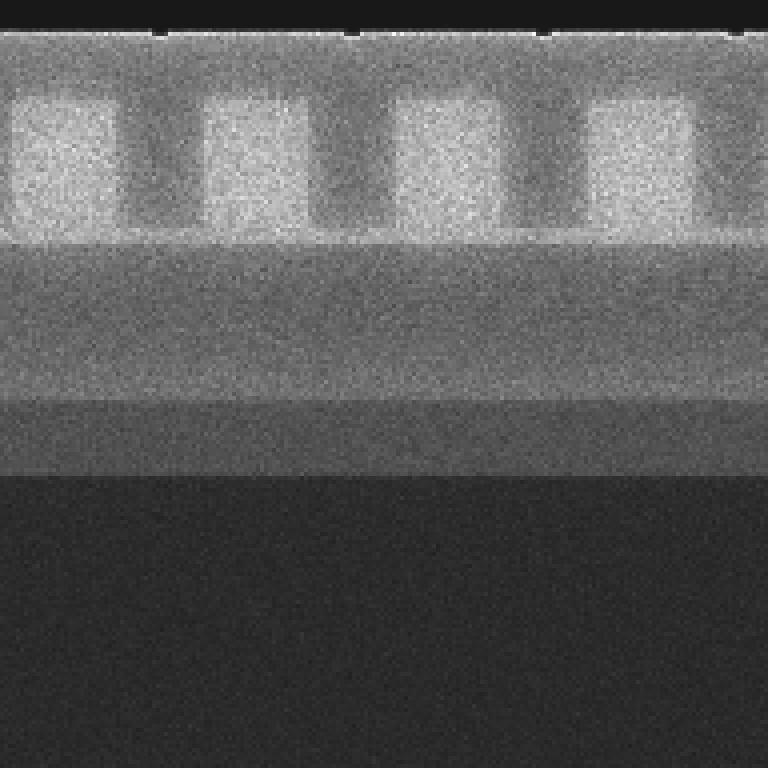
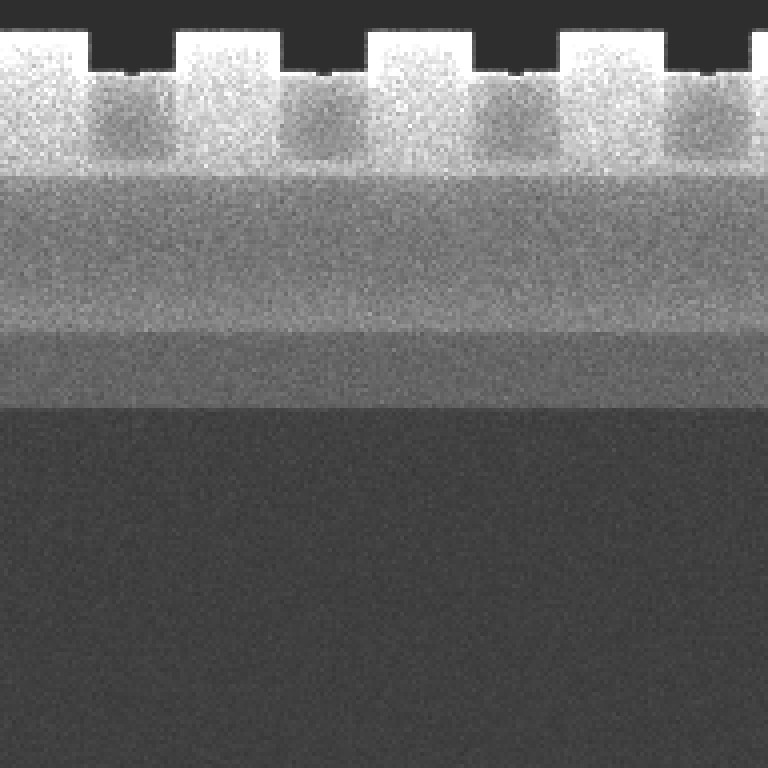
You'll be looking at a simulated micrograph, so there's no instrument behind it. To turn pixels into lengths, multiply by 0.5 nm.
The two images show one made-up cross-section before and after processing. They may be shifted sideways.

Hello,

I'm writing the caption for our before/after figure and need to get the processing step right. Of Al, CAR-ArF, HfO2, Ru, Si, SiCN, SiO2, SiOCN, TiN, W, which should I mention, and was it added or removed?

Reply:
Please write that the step removed W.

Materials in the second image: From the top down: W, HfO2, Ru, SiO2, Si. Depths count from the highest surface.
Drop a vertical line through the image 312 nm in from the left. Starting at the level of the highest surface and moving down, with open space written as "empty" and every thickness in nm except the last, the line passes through HfO2 72, Ru 78, SiO2 38, Si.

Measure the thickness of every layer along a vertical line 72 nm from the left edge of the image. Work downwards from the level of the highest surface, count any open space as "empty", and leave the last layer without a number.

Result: empty 20, W 44, HfO2 8, Ru 78, SiO2 38, Si